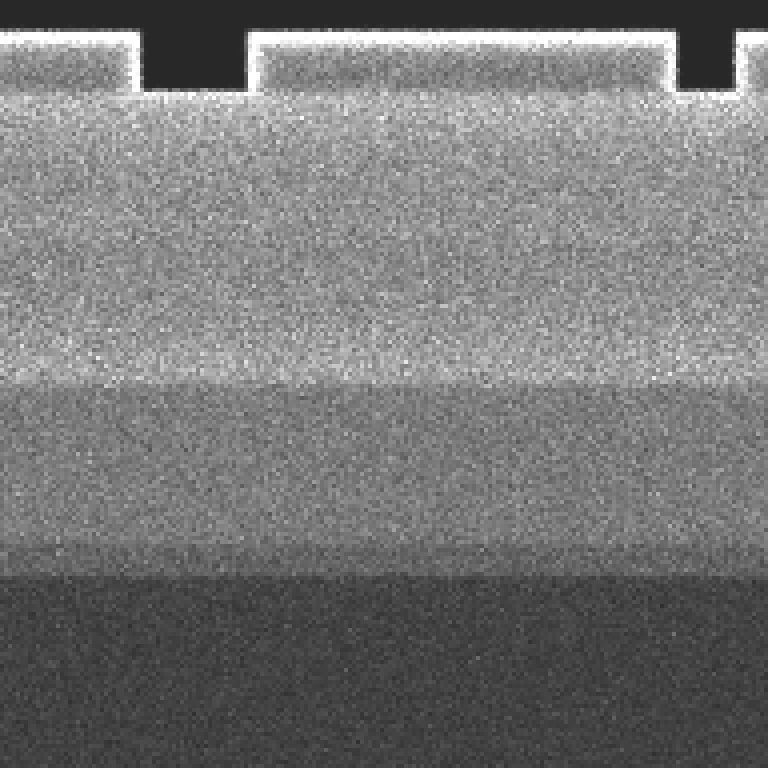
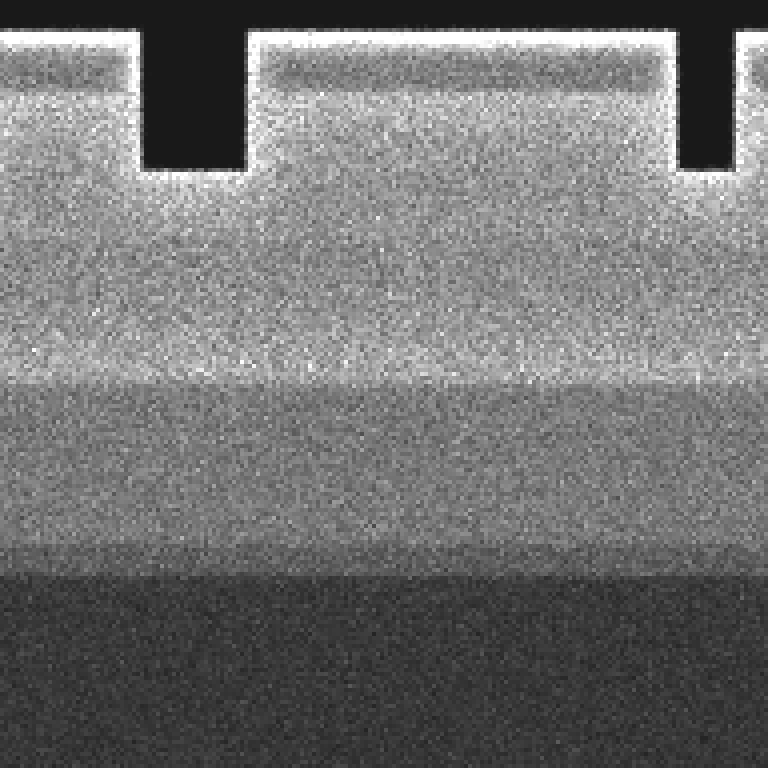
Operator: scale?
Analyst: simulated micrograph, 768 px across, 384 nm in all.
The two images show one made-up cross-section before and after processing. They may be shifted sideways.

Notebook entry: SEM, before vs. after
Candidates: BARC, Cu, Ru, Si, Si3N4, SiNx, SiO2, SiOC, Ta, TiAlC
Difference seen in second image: Ru removed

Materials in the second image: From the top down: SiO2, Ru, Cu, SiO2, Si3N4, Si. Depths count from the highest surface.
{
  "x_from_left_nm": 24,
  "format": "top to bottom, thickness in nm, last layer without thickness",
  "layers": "SiO2 30, Ru 74, Cu 72, SiO2 80, Si3N4 16, Si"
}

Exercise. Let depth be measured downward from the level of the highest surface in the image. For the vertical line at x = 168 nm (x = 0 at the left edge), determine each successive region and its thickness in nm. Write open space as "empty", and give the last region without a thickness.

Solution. SiO2 30, Ru 74, Cu 72, SiO2 80, Si3N4 16, Si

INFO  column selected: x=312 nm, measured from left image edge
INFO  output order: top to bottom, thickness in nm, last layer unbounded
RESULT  SiO2 30, Ru 74, Cu 72, SiO2 80, Si3N4 16, Si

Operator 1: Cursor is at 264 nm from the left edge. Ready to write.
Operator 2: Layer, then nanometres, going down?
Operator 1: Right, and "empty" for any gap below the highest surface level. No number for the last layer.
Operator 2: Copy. SiO2 30, Ru 74, Cu 72, SiO2 80, Si3N4 16, Si